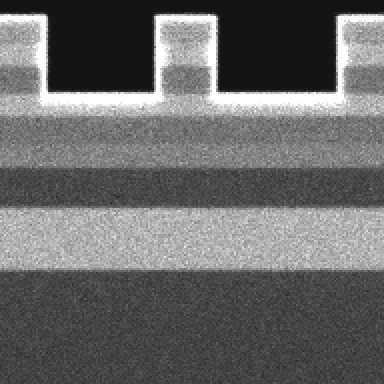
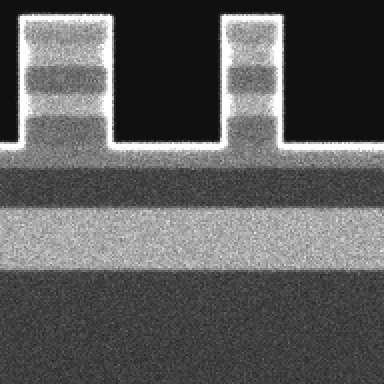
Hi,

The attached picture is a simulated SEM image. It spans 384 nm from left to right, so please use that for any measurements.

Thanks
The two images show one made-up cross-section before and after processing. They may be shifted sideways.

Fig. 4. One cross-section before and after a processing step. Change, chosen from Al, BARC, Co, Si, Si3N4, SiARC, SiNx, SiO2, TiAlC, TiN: SiNx and SiO2 removed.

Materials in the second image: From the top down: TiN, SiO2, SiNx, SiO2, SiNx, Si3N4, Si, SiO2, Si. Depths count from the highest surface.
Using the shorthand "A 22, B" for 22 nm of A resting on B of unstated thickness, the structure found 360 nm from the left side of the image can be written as empty 128, Si3N4 24, Si 40, SiO2 62, Si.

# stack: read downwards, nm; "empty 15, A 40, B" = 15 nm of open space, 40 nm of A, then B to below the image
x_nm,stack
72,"TiN 28, SiO2 22, SiNx 28, SiO2 22, SiNx 28, Si3N4 24, Si 40, SiO2 62, Si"